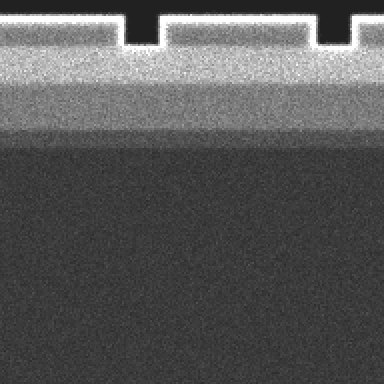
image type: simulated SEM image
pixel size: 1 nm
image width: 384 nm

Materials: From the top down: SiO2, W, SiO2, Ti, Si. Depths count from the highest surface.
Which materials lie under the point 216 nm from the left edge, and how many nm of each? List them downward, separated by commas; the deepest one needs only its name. SiO2 30, W 38, SiO2 46, Ti 18, Si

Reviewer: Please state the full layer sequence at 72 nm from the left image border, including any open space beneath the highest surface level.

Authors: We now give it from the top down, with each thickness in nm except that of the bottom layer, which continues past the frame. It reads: SiO2 30, W 38, SiO2 46, Ti 18, Si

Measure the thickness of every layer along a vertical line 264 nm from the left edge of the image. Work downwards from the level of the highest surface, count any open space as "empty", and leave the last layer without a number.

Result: SiO2 30, W 38, SiO2 46, Ti 18, Si